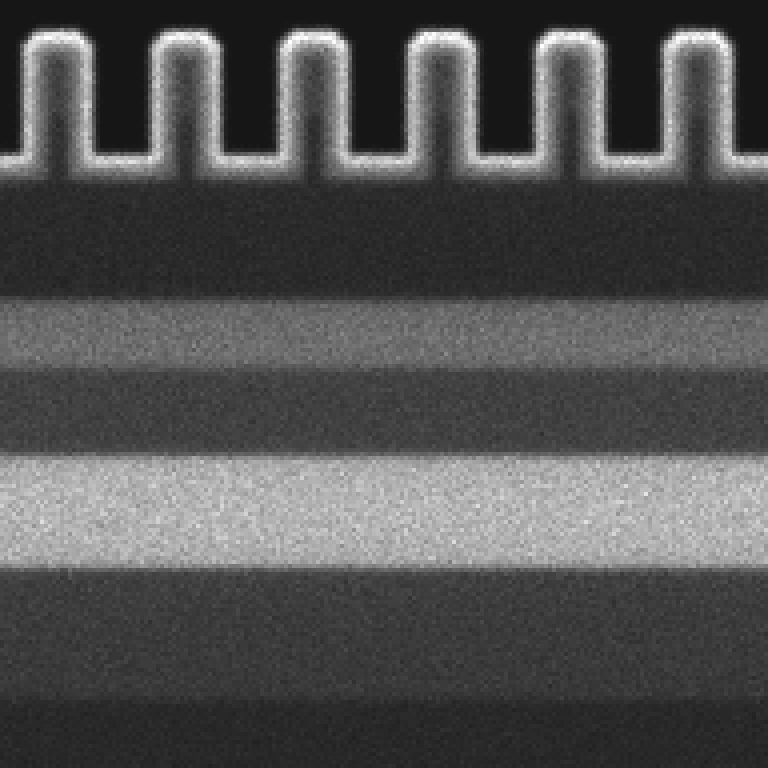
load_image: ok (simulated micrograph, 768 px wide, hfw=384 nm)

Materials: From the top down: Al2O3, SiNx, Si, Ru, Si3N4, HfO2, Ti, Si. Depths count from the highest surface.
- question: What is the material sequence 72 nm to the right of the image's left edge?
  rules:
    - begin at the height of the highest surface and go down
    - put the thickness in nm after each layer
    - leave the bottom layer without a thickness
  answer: empty 62, Al2O3 12, Si 60, Ru 34, Si3N4 44, HfO2 56, Ti 66, Si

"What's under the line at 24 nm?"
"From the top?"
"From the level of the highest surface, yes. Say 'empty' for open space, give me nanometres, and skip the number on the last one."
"Al2O3 12, SiNx 30, Si 92, Ru 34, Si3N4 44, HfO2 56, Ti 66, Si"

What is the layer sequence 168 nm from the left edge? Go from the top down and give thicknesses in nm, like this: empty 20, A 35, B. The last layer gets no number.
empty 2, Al2O3 72, Si 60, Ru 34, Si3N4 44, HfO2 56, Ti 66, Si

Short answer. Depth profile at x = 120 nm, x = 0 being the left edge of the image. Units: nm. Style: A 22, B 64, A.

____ empty 62, Al2O3 12, Si 60, Ru 34, Si3N4 44, HfO2 56, Ti 66, Si